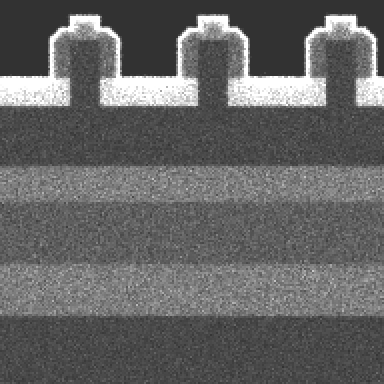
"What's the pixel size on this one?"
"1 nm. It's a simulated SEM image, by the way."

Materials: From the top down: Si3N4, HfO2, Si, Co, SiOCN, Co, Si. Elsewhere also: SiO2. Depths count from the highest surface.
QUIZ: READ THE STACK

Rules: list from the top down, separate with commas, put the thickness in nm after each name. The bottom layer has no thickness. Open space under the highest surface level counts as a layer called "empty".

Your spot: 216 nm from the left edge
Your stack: SiO2 24, Si 126, Co 36, SiOCN 62, Co 52, Si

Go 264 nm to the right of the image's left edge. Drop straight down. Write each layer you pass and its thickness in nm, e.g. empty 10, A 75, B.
empty 62, HfO2 28, Si 60, Co 36, SiOCN 62, Co 52, Si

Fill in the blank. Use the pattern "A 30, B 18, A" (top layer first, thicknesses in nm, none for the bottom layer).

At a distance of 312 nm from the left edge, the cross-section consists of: empty 16, Si3N4 46, HfO2 28, Si 60, Co 36, SiOCN 62, Co 52, Si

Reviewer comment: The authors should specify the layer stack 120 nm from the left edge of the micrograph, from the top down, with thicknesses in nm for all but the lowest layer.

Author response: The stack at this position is empty 62, HfO2 28, Si 60, Co 36, SiOCN 62, Co 52, Si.